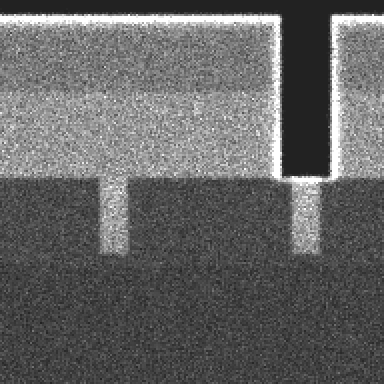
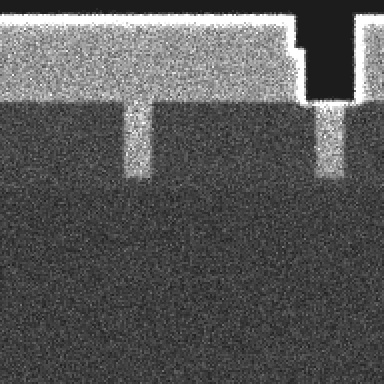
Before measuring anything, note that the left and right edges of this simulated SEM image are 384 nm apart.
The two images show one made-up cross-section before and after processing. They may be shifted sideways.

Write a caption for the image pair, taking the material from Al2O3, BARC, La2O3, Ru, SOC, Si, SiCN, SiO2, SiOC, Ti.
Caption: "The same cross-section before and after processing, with SOC removed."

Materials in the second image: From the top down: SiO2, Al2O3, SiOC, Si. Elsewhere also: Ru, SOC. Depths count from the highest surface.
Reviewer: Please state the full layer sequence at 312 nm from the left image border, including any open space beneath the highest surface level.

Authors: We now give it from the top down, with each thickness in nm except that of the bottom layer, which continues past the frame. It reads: empty 86, SiOC 88, Si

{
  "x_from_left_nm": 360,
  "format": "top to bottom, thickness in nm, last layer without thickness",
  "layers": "SiO2 72, Al2O3 14, SiOC 88, Si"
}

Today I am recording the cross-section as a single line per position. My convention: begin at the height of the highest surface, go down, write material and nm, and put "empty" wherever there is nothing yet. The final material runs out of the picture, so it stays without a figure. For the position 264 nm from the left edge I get SiO2 72, Al2O3 14, SiOC 88, Si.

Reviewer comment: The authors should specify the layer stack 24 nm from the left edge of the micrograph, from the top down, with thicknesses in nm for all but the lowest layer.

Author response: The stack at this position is SiO2 72, Al2O3 14, SiOC 88, Si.